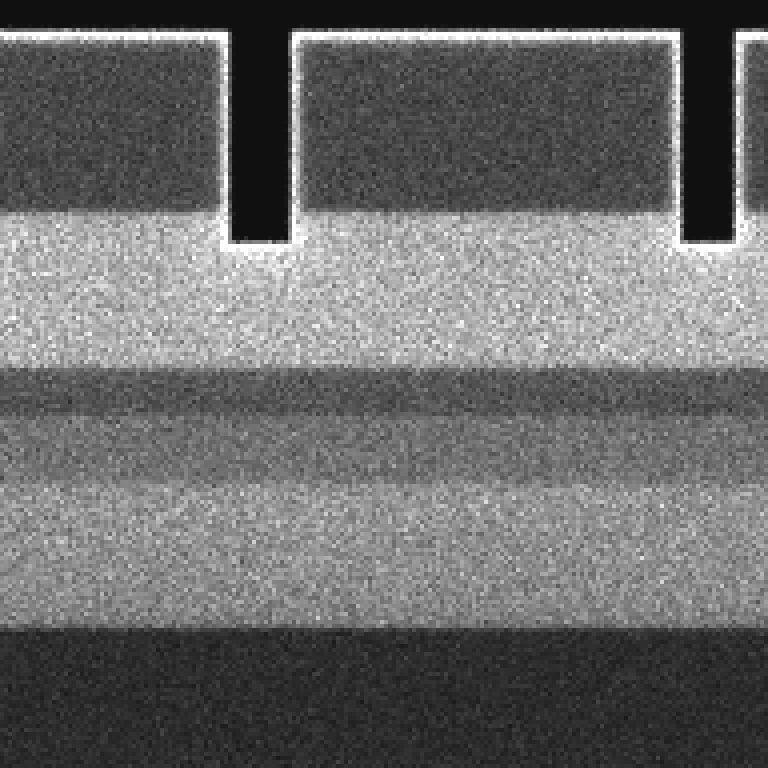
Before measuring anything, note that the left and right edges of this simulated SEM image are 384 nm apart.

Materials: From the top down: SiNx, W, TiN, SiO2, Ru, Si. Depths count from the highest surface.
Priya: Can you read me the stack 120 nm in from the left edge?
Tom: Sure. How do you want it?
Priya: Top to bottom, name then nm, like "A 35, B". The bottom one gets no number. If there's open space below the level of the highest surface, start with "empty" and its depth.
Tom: empty 106, W 62, TiN 24, SiO2 34, Ru 72, Si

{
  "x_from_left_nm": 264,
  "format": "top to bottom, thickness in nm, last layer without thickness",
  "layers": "SiNx 90, W 78, TiN 24, SiO2 34, Ru 72, Si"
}